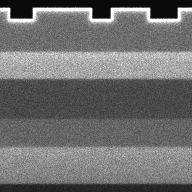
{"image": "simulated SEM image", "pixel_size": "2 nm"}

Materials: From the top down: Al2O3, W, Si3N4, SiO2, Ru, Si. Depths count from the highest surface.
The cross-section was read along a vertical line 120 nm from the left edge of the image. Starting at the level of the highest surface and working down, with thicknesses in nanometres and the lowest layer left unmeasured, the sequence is Al2O3 88, W 54, Si3N4 80, SiO2 56, Ru 74, Si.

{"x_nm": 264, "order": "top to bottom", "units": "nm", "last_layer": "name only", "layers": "Al2O3 88, W 54, Si3N4 80, SiO2 56, Ru 74, Si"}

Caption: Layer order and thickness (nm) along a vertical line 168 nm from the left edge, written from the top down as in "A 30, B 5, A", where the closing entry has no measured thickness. Al2O3 88, W 54, Si3N4 80, SiO2 56, Ru 74, Si